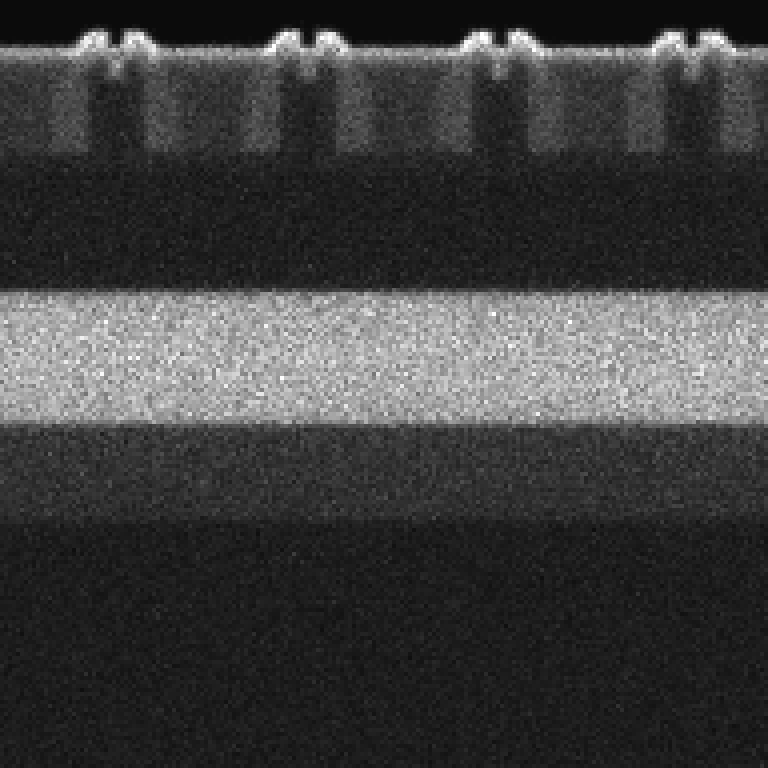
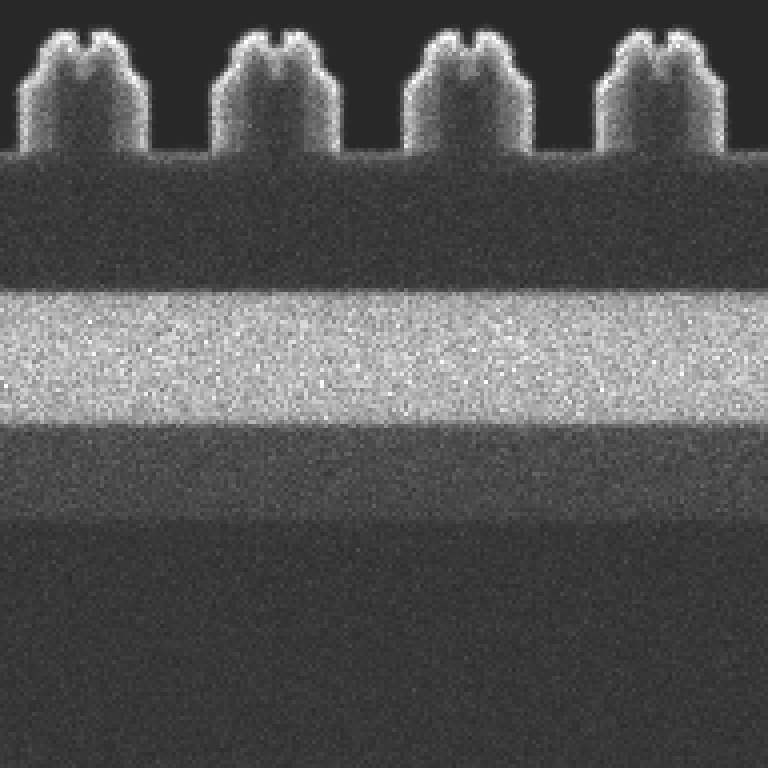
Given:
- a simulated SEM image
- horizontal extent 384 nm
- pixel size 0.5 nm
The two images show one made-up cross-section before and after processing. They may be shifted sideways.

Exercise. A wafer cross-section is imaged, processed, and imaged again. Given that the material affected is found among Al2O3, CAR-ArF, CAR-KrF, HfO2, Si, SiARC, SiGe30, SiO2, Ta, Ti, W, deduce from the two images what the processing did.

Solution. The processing removed SiARC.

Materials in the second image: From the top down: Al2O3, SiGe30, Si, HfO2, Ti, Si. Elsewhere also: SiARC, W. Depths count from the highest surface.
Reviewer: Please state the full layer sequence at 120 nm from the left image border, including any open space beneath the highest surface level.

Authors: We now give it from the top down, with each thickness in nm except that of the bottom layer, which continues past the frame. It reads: empty 4, Al2O3 56, SiGe30 10, Si 60, HfO2 66, Ti 48, Si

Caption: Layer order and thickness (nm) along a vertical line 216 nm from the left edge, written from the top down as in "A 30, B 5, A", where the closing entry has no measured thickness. empty 4, Al2O3 56, SiGe30 10, Si 60, HfO2 66, Ti 48, Si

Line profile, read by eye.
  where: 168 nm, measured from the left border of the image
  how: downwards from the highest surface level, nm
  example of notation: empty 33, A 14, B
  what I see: empty 26, Al2O3 34, SiGe30 10, Si 60, HfO2 66, Ti 48, Si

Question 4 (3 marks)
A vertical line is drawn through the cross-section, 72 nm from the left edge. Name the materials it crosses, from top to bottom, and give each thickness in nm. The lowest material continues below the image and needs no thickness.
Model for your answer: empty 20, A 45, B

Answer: empty 26, Al2O3 34, SiGe30 10, Si 60, HfO2 66, Ti 48, Si